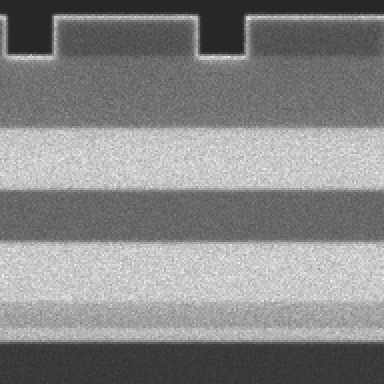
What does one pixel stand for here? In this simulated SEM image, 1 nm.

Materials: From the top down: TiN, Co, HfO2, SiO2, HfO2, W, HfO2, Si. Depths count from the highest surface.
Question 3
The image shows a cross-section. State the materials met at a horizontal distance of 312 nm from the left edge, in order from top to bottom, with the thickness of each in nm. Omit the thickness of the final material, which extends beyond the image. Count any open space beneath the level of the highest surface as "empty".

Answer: TiN 40, Co 72, HfO2 62, SiO2 52, HfO2 60, W 26, HfO2 14, Si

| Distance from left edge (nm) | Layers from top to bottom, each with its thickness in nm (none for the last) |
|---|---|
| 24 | empty 40, Co 72, HfO2 62, SiO2 52, HfO2 60, W 26, HfO2 14, Si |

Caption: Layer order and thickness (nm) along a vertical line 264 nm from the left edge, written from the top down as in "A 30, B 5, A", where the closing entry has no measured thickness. TiN 40, Co 72, HfO2 62, SiO2 52, HfO2 60, W 26, HfO2 14, Si